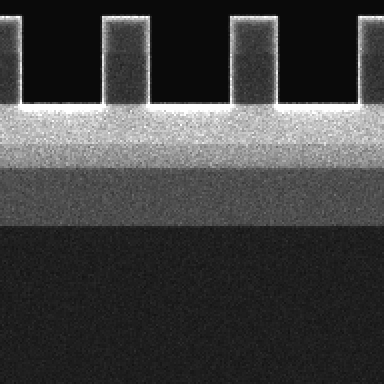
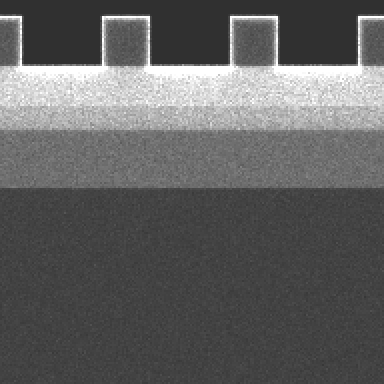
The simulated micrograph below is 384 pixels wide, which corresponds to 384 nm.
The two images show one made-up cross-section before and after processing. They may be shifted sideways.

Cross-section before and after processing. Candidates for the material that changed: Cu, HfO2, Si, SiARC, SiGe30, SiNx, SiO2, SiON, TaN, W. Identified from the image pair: SiARC (removed).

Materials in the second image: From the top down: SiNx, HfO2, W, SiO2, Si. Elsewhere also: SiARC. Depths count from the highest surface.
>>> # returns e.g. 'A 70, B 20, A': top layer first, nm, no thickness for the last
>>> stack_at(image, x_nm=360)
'SiNx 50, HfO2 40, W 24, SiO2 58, Si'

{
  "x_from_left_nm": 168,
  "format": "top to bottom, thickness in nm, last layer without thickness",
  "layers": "empty 50, HfO2 40, W 24, SiO2 58, Si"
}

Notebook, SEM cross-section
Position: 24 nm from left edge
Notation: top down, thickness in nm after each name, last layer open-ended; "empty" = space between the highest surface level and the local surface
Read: empty 50, HfO2 40, W 24, SiO2 58, Si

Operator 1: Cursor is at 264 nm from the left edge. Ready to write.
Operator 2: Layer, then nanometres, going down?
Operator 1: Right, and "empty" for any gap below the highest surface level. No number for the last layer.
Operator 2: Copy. SiNx 50, HfO2 40, W 24, SiO2 58, Si